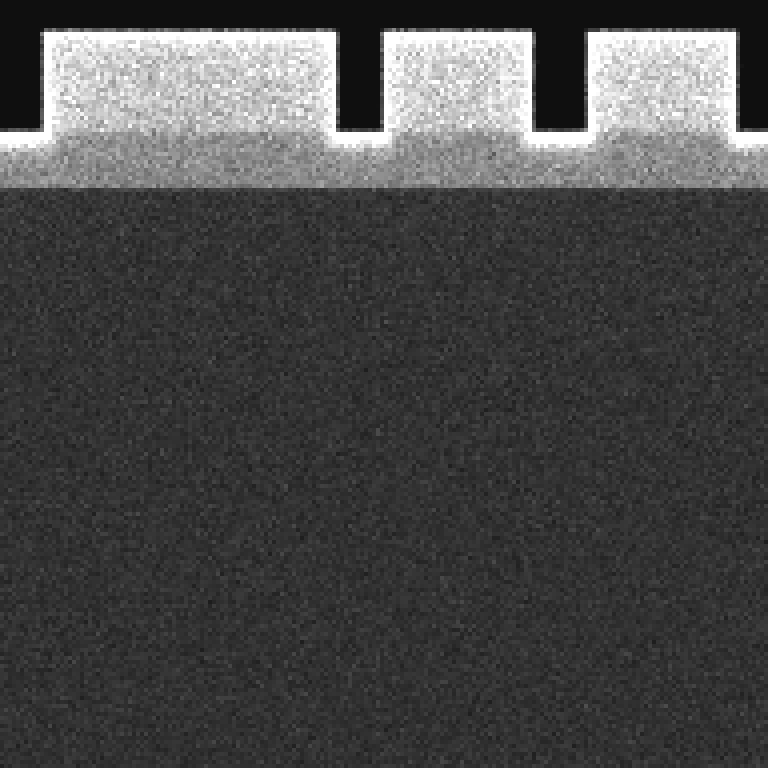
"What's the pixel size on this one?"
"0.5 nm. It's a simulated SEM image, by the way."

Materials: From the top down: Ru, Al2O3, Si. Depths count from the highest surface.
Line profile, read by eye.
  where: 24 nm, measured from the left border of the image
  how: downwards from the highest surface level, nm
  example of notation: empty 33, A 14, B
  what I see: Ru 50, Al2O3 28, Si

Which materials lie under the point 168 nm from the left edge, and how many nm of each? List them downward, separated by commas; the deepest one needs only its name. empty 50, Al2O3 28, Si